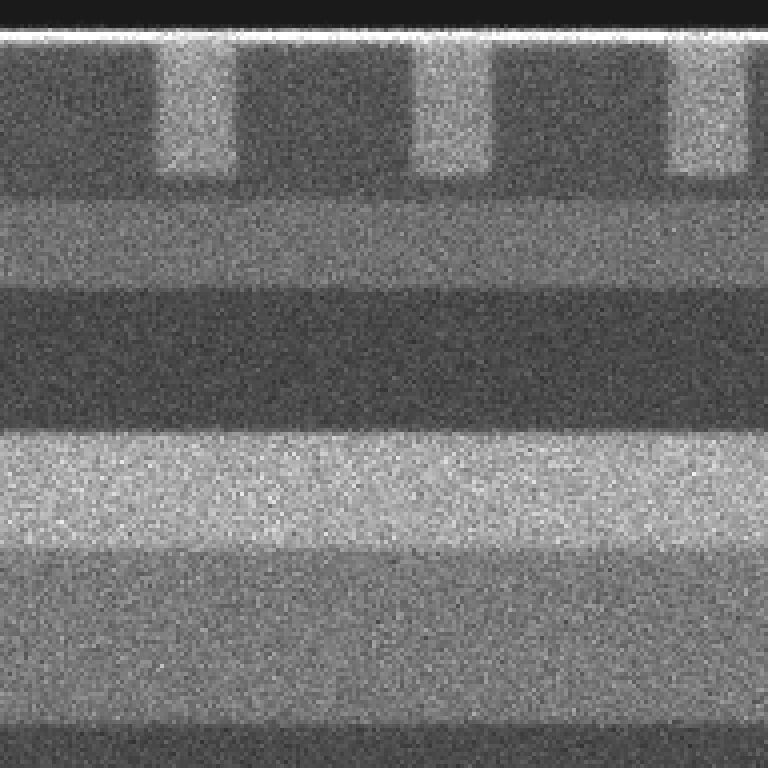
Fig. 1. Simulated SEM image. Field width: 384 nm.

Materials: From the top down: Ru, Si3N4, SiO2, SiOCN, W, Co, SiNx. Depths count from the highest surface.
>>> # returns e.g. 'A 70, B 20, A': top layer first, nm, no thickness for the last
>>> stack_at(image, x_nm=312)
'Si3N4 84, SiO2 44, SiOCN 72, W 58, Co 88, SiNx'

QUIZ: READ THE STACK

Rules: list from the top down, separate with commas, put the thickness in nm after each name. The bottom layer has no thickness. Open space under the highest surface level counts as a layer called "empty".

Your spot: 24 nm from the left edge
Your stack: Si3N4 84, SiO2 44, SiOCN 72, W 58, Co 88, SiNx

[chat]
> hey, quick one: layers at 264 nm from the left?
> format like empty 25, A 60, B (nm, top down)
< Si3N4 84, SiO2 44, SiOCN 72, W 58, Co 88, SiNx